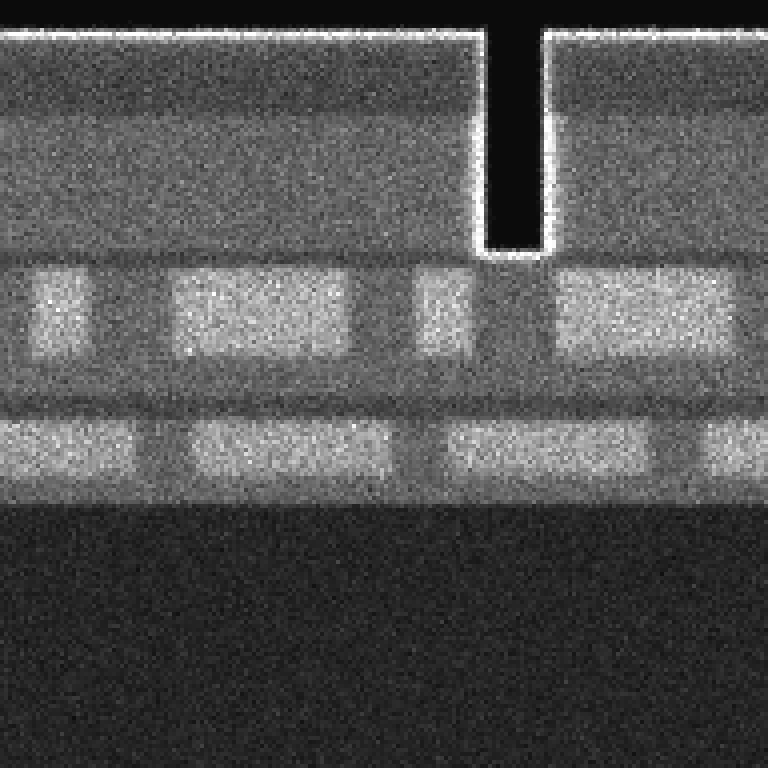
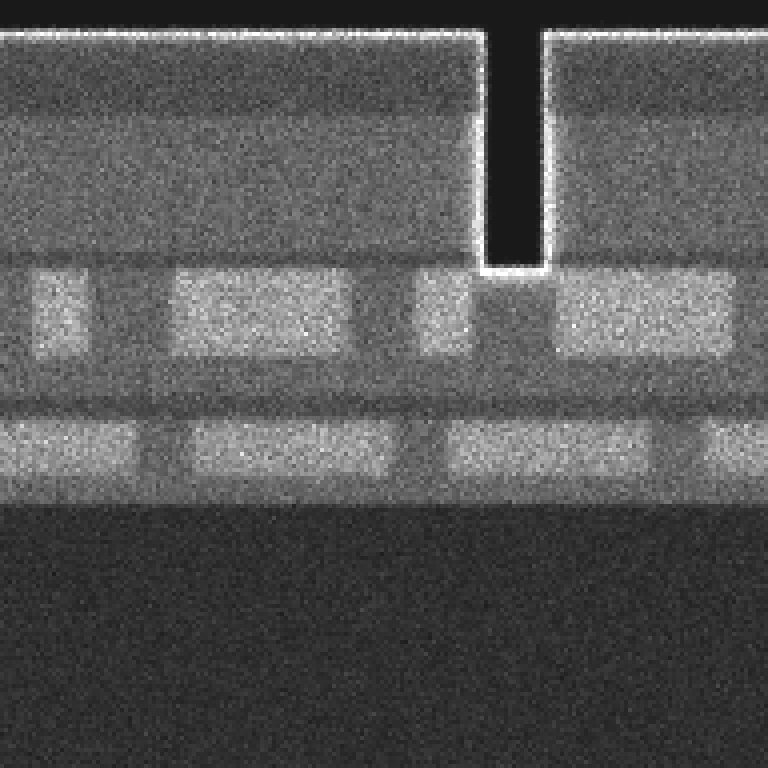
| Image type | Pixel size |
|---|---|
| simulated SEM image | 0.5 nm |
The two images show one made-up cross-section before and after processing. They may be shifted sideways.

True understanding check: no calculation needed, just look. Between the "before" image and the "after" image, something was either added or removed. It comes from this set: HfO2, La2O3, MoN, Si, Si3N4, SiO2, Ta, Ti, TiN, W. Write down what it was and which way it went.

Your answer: Si3N4 (removed)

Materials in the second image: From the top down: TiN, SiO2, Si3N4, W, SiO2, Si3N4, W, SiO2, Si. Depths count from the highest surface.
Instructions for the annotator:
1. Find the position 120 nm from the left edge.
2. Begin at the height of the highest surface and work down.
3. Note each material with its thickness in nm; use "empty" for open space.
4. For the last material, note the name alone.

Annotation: TiN 42, SiO2 68, Si3N4 8, W 44, SiO2 20, Si3N4 12, W 28, SiO2 14, Si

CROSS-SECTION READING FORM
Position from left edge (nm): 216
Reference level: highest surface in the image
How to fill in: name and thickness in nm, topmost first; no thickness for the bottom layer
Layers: TiN 42, SiO2 68, Si3N4 8, W 44, SiO2 20, Si3N4 12, SiO2 42, Si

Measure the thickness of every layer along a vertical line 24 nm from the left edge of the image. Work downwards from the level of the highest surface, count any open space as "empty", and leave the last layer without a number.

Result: TiN 42, SiO2 68, Si3N4 8, W 44, SiO2 20, Si3N4 12, W 28, SiO2 14, Si